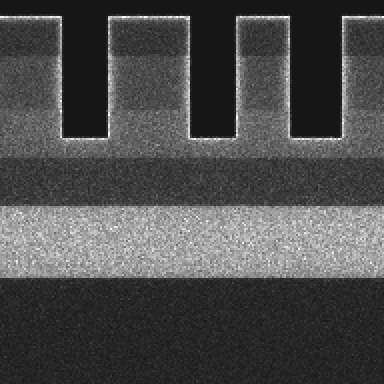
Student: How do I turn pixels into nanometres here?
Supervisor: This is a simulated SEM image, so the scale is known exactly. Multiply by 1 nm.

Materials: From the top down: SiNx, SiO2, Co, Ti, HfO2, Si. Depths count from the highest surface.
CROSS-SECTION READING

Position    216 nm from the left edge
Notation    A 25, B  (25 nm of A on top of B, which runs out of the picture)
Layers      empty 122, Co 20, Ti 48, HfO2 72, Si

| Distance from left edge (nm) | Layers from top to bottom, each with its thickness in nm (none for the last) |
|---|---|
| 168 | SiNx 40, SiO2 54, Co 48, Ti 48, HfO2 72, Si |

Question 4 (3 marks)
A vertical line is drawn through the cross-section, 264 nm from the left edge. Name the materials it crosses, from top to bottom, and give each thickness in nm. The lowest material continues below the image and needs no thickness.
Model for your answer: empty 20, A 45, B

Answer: SiNx 40, SiO2 54, Co 48, Ti 48, HfO2 72, Si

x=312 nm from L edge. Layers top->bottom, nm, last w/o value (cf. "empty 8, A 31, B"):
empty 122, Co 20, Ti 48, HfO2 72, Si